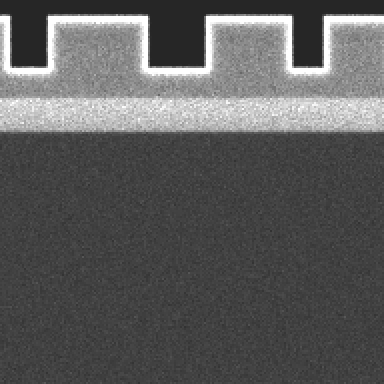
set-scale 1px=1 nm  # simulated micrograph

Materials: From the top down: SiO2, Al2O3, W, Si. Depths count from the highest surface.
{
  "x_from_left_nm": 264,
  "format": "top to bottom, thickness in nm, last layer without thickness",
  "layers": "SiO2 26, Al2O3 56, W 34, Si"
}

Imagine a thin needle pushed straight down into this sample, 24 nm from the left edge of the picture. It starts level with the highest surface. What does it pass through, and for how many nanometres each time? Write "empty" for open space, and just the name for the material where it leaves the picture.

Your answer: empty 52, Al2O3 30, W 34, Si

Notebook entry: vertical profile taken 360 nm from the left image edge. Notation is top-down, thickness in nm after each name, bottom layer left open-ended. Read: SiO2 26, Al2O3 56, W 34, Si